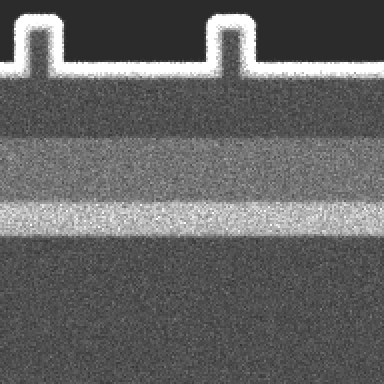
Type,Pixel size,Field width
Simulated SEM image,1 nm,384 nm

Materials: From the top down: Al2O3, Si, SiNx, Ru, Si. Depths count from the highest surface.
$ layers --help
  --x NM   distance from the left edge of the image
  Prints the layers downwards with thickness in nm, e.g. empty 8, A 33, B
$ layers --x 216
Al2O3 62, Si 60, SiNx 64, Ru 34, Si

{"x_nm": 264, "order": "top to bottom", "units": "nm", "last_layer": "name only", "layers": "empty 48, Al2O3 14, Si 60, SiNx 64, Ru 34, Si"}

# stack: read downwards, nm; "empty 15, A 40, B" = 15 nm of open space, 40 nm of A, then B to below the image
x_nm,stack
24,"Al2O3 62, Si 60, SiNx 64, Ru 34, Si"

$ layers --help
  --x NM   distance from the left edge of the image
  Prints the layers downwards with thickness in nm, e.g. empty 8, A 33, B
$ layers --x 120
empty 48, Al2O3 14, Si 60, SiNx 64, Ru 34, Si